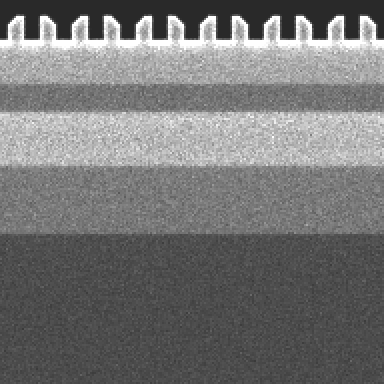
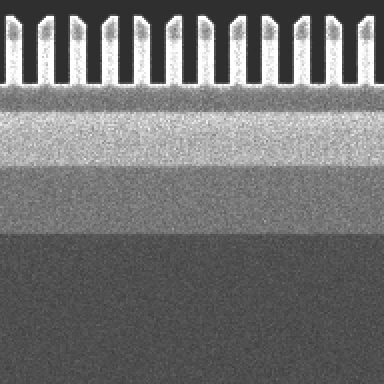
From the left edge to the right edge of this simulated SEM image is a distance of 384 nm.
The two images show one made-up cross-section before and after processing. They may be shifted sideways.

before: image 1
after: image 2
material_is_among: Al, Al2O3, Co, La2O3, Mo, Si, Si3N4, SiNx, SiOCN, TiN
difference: Al2O3, removed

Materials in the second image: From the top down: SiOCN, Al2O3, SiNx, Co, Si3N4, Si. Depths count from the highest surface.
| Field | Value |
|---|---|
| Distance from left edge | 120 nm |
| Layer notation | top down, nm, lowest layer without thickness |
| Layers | empty 68, SiNx 28, Co 54, Si3N4 68, Si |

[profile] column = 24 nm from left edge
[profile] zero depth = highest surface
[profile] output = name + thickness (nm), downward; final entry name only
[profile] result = empty 68, SiNx 28, Co 54, Si3N4 68, Si